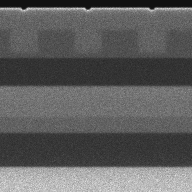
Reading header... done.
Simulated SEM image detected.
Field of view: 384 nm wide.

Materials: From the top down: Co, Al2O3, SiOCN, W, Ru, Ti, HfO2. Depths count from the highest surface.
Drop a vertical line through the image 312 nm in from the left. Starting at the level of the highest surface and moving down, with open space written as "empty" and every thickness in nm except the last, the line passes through Co 90, Al2O3 10, SiOCN 56, W 62, Ru 32, Ti 68, HfO2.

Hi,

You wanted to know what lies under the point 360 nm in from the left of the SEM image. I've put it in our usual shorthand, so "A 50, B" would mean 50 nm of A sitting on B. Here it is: Co 44, Al2O3 56, SiOCN 56, W 62, Ru 32, Ti 68, HfO2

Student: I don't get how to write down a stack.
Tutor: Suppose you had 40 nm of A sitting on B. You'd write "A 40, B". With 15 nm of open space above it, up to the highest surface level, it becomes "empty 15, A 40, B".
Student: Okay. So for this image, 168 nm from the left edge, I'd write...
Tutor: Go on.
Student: Co 90, Al2O3 10, SiOCN 56, W 62, Ru 32, Ti 68, HfO2